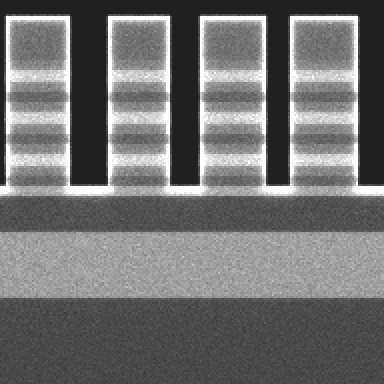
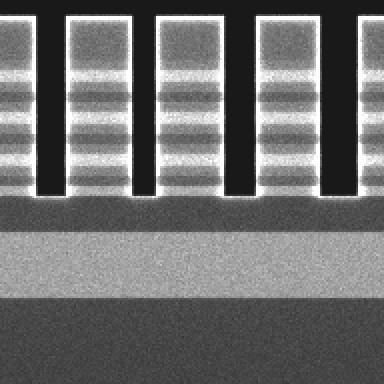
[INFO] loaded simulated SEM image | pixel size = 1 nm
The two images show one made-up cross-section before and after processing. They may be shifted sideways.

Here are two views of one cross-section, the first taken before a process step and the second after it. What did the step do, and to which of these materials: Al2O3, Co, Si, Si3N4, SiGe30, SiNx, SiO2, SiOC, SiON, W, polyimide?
It removed Al2O3.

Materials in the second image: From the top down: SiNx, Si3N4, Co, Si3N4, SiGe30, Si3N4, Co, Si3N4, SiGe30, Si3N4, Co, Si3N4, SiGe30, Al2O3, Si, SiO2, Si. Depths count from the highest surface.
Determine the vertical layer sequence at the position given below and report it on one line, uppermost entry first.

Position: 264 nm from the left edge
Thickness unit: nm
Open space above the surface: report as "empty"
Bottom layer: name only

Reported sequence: SiNx 44, Si3N4 10, Co 12, Si3N4 10, SiGe30 10, Si3N4 10, Co 12, Si3N4 10, SiGe30 10, Si3N4 10, Co 12, Si3N4 10, SiGe30 10, Al2O3 10, Si 36, SiO2 66, Si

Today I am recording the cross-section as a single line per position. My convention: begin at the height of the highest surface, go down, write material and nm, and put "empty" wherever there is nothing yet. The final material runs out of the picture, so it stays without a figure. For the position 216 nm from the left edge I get SiNx 44, Si3N4 10, Co 12, Si3N4 10, SiGe30 10, Si3N4 10, Co 12, Si3N4 10, SiGe30 10, Si3N4 10, Co 12, Si3N4 10, SiGe30 10, Al2O3 10, Si 36, SiO2 66, Si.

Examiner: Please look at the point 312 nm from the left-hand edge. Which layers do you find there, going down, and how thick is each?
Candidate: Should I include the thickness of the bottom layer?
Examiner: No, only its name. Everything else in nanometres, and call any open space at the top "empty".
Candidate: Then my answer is SiNx 44, Si3N4 10, Co 12, Si3N4 10, SiGe30 10, Si3N4 10, Co 12, Si3N4 10, SiGe30 10, Si3N4 10, Co 12, Si3N4 10, SiGe30 10, Al2O3 10, Si 36, SiO2 66, Si